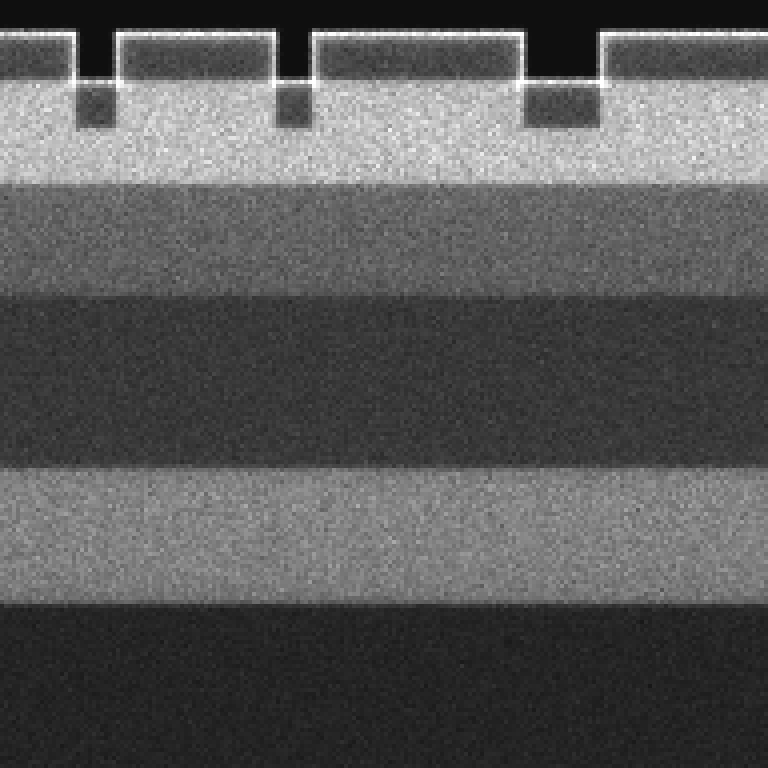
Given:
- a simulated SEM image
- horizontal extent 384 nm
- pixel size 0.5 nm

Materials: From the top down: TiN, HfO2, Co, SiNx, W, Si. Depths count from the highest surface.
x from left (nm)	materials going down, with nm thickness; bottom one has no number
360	TiN 24, HfO2 52, Co 56, SiNx 86, W 68, Si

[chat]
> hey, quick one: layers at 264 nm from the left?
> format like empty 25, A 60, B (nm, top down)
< empty 24, TiN 24, HfO2 28, Co 56, SiNx 86, W 68, Si